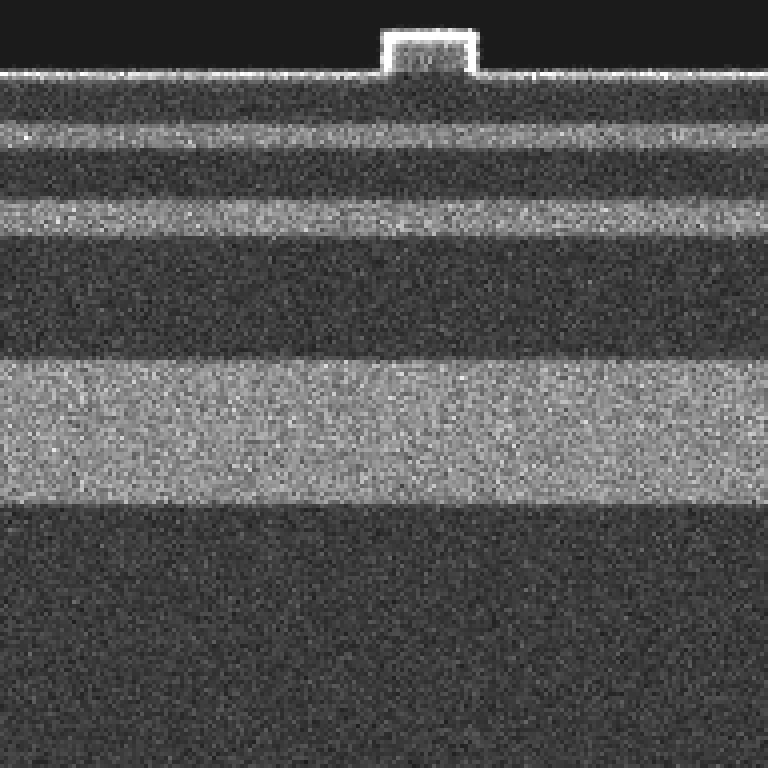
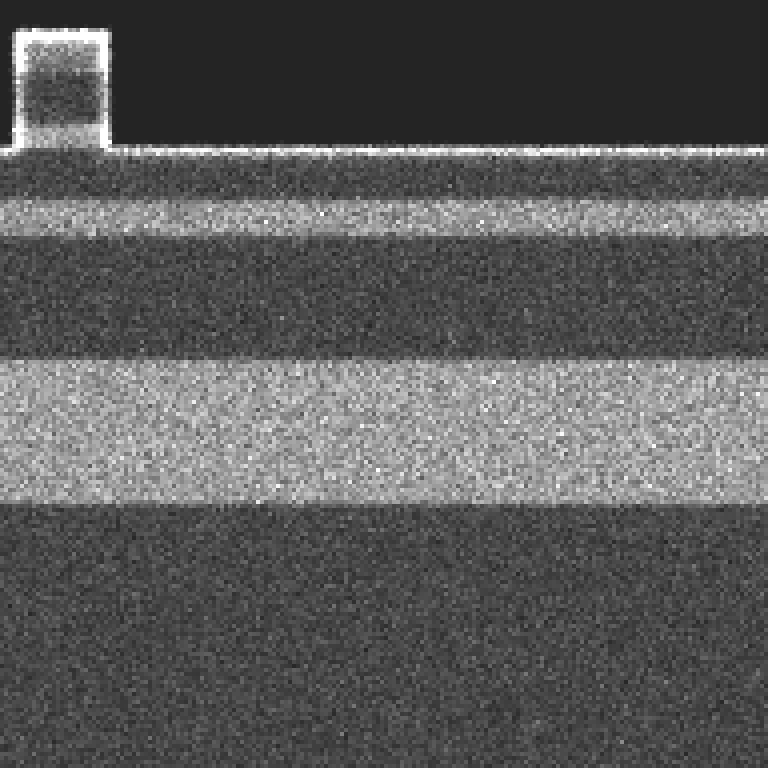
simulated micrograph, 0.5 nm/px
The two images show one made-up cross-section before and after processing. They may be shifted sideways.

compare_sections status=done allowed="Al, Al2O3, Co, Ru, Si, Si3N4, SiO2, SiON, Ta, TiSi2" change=removed material="Co and Si"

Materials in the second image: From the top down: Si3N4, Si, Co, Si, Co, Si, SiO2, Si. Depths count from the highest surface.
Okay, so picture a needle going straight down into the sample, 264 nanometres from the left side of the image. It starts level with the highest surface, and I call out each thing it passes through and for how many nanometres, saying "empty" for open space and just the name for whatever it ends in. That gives empty 58, Si 26, Co 18, Si 62, SiO2 72, Si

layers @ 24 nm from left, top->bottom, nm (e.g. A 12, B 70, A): Si3N4 20, Si 26, Co 12, Si 26, Co 18, Si 62, SiO2 72, Si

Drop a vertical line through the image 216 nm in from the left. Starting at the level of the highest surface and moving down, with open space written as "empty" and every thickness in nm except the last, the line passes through empty 58, Si 26, Co 18, Si 62, SiO2 72, Si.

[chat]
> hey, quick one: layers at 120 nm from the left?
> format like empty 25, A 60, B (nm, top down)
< empty 58, Si 26, Co 18, Si 62, SiO2 72, Si